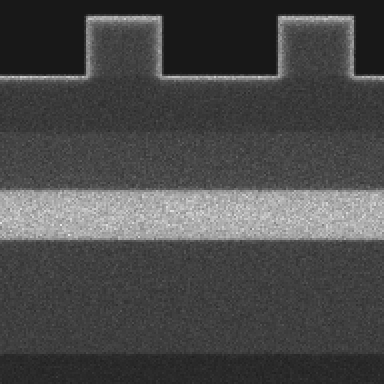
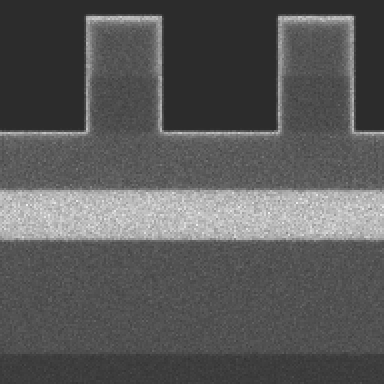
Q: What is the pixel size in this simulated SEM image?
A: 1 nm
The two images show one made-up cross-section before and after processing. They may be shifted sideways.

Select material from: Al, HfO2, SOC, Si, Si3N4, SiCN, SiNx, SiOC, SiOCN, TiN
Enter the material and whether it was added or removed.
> SiNx / removed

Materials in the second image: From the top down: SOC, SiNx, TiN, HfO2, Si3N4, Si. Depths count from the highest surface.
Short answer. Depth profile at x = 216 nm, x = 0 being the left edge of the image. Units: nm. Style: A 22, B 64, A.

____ empty 116, TiN 58, HfO2 50, Si3N4 114, Si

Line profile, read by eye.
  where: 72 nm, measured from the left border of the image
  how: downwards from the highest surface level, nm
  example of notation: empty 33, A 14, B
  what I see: empty 116, TiN 58, HfO2 50, Si3N4 114, Si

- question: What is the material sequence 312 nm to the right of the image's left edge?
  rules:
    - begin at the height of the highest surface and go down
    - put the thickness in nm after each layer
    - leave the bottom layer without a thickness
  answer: SOC 60, SiNx 56, TiN 58, HfO2 50, Si3N4 114, Si